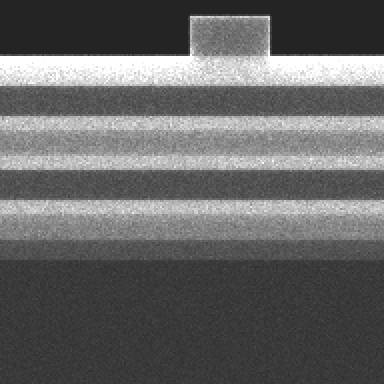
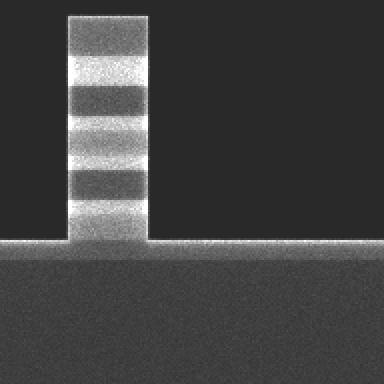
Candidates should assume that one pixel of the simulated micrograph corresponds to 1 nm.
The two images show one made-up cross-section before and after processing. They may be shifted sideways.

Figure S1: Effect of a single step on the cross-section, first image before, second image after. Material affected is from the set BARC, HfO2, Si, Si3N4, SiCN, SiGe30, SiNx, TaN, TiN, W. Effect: removed HfO2 and SiNx and W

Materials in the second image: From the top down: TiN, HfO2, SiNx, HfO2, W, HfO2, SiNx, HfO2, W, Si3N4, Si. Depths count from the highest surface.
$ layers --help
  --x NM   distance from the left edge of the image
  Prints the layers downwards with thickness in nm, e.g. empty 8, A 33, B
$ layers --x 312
empty 224, Si3N4 20, Si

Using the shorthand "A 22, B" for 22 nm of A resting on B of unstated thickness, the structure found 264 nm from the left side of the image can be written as empty 224, Si3N4 20, Si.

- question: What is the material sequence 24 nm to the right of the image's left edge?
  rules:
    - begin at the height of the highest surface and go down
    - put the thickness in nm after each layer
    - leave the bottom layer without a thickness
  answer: empty 224, Si3N4 20, Si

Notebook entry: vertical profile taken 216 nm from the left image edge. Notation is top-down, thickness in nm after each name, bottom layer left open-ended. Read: empty 224, Si3N4 20, Si